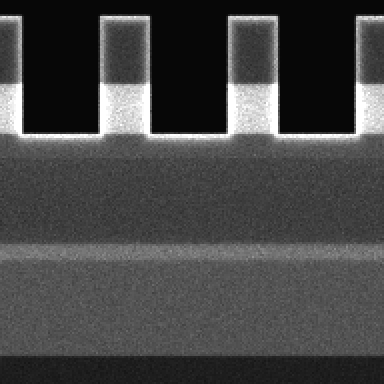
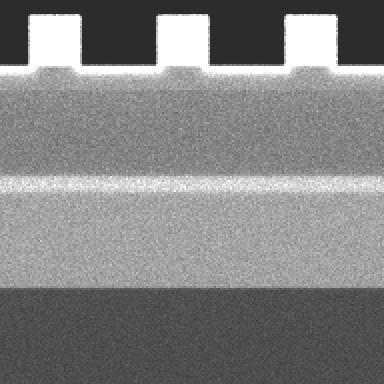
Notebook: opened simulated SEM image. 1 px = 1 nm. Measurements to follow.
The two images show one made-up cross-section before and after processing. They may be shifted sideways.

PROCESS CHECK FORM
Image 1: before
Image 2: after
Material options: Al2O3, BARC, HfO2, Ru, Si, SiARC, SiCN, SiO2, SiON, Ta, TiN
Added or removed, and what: removed, SiARC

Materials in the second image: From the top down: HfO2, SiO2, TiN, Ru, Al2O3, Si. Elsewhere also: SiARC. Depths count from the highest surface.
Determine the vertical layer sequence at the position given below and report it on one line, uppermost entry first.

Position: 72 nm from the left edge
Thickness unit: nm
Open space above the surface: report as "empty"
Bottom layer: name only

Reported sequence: HfO2 50, SiO2 24, TiN 86, Ru 16, Al2O3 96, Si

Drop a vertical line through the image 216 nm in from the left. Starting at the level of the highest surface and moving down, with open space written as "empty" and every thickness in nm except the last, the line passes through empty 50, SiO2 24, TiN 86, Ru 16, Al2O3 96, Si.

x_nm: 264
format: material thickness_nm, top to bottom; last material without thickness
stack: empty 50, SiO2 24, TiN 86, Ru 16, Al2O3 96, Si